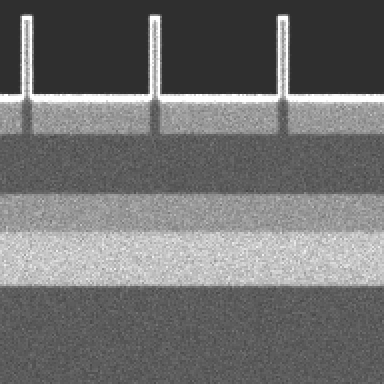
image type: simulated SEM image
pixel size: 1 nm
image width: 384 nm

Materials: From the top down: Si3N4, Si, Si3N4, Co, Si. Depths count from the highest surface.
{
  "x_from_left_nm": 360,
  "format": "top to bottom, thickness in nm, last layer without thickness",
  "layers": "empty 80, Si3N4 38, Si 60, Si3N4 38, Co 54, Si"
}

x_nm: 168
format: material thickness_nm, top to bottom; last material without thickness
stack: empty 80, Si3N4 38, Si 60, Si3N4 38, Co 54, Si